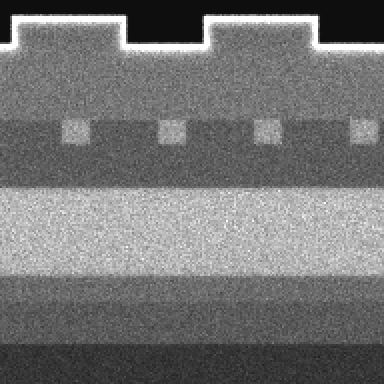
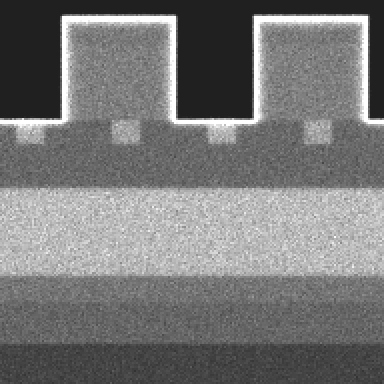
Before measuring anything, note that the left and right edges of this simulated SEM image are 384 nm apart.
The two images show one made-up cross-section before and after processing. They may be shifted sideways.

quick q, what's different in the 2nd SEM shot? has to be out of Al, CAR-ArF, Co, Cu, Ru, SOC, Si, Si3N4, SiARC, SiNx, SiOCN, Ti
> SOC removed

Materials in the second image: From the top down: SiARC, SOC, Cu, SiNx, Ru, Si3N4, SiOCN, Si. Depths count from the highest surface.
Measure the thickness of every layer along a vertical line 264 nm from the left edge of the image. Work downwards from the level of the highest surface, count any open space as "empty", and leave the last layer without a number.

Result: SiARC 28, SOC 76, SiNx 68, Ru 88, Si3N4 26, SiOCN 42, Si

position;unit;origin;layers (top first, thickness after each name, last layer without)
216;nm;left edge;empty 104, Cu 24, SiNx 44, Ru 88, Si3N4 26, SiOCN 42, Si